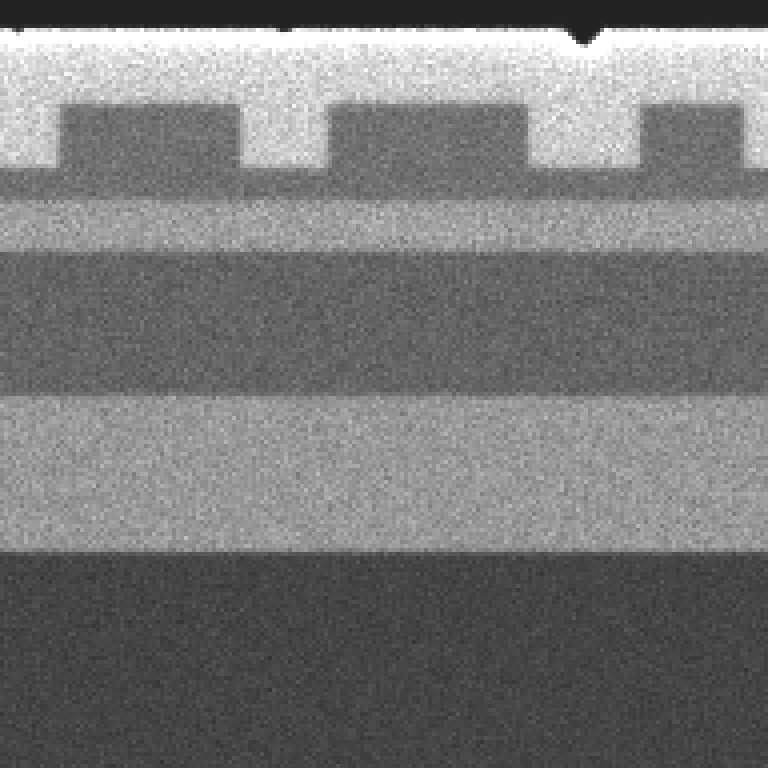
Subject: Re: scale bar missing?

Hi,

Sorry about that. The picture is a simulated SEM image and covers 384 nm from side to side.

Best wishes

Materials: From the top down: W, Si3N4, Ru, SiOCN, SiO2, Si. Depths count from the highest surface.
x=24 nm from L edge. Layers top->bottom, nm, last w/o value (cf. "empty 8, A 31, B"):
W 68, Si3N4 16, Ru 26, SiOCN 72, SiO2 78, Si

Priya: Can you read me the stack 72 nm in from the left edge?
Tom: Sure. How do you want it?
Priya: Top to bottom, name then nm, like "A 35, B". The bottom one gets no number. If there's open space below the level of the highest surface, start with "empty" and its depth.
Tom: W 36, Si3N4 48, Ru 26, SiOCN 72, SiO2 78, Si